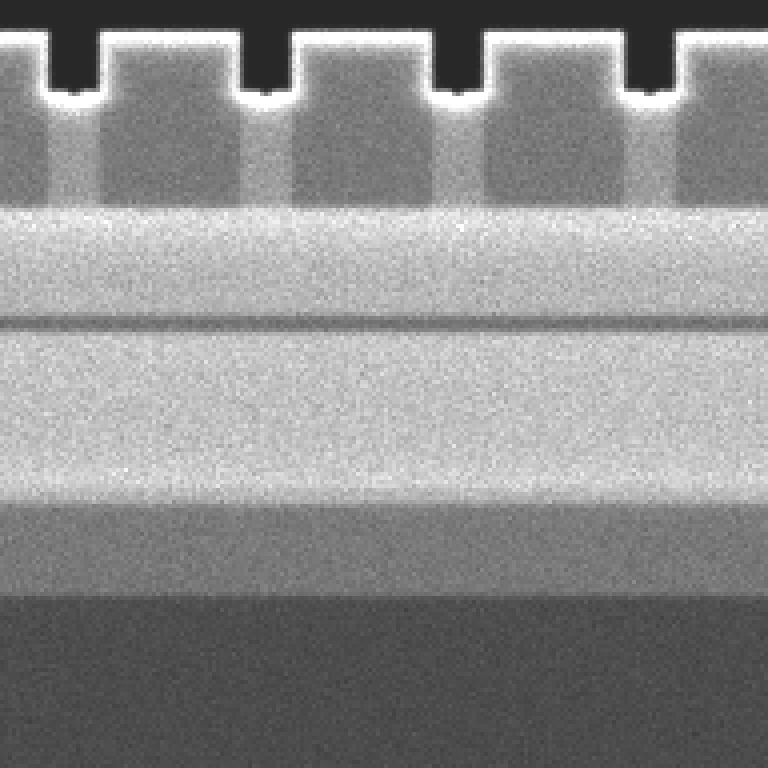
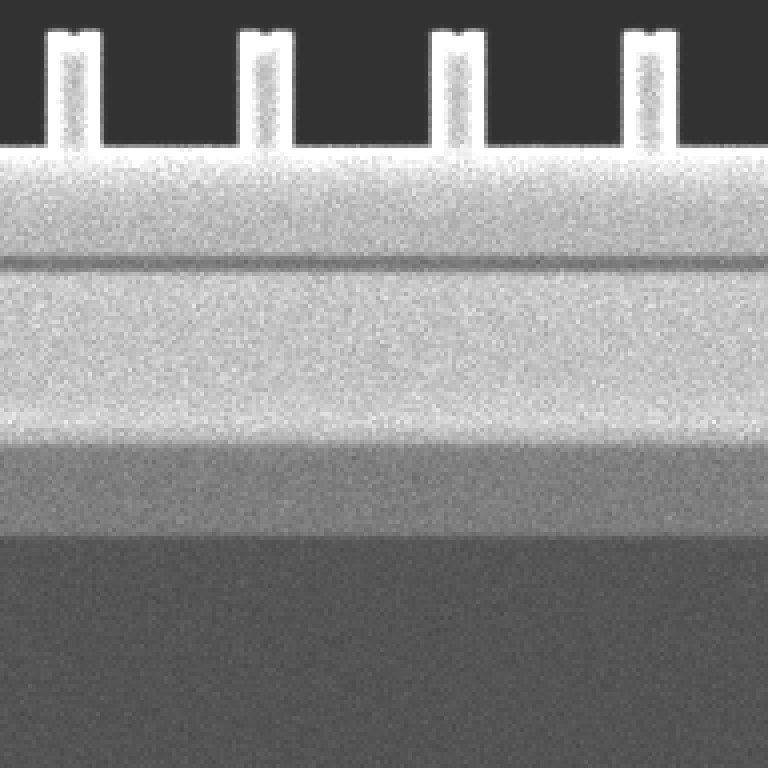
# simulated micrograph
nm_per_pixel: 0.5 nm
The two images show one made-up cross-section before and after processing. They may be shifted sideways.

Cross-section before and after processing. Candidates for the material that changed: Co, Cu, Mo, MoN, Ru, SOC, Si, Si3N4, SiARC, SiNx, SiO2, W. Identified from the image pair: SOC (removed).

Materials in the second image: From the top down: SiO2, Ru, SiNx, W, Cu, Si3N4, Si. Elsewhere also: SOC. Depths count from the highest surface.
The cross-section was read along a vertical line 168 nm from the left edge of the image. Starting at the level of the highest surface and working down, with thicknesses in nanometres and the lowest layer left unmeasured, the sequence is empty 58, Ru 54, SiNx 8, W 78, Cu 8, Si3N4 46, Si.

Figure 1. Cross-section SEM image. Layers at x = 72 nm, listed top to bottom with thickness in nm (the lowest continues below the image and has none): empty 58, Ru 54, SiNx 8, W 78, Cu 8, Si3N4 46, Si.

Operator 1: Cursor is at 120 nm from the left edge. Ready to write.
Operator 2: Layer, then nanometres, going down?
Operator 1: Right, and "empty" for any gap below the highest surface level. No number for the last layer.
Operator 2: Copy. SiO2 58, Ru 54, SiNx 8, W 78, Cu 8, Si3N4 46, Si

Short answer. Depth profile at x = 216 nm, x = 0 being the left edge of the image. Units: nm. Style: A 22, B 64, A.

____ SiO2 58, Ru 54, SiNx 8, W 78, Cu 8, Si3N4 46, Si